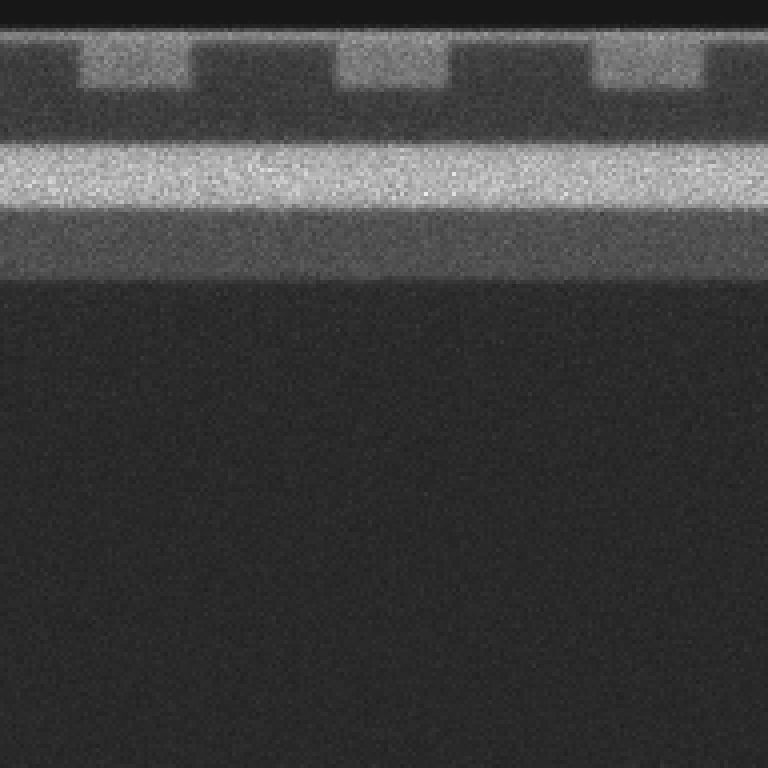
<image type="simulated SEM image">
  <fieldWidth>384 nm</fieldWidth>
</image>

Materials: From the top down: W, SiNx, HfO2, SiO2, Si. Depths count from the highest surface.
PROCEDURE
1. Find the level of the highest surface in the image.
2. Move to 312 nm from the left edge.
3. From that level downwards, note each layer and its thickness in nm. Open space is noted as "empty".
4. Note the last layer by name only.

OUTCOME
W 28, SiNx 28, HfO2 32, SiO2 36, Si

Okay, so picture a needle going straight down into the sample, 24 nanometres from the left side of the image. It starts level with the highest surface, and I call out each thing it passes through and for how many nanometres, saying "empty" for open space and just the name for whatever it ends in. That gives SiNx 56, HfO2 32, SiO2 36, Si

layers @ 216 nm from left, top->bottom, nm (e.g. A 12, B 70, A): W 28, SiNx 28, HfO2 32, SiO2 36, Si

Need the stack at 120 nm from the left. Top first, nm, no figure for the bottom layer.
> SiNx 56, HfO2 32, SiO2 36, Si